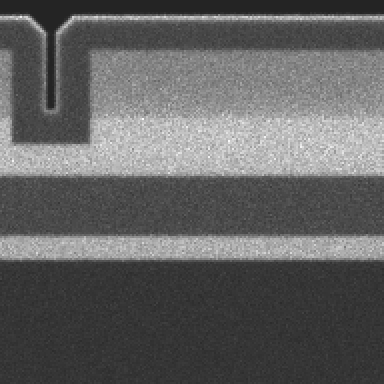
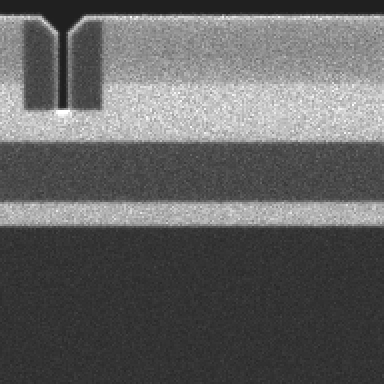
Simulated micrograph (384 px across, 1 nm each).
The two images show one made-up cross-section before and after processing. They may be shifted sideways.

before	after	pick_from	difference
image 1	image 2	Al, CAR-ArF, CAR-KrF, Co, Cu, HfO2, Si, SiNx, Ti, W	SiNx removed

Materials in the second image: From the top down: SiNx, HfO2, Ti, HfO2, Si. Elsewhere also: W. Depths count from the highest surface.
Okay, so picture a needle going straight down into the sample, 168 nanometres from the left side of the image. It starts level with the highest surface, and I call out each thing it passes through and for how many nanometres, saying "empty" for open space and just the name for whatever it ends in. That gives W 68, HfO2 58, Ti 60, HfO2 24, Si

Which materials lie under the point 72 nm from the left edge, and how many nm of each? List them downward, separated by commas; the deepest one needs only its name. empty 12, SiNx 82, HfO2 32, Ti 60, HfO2 24, Si